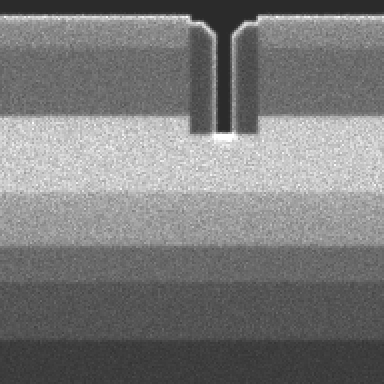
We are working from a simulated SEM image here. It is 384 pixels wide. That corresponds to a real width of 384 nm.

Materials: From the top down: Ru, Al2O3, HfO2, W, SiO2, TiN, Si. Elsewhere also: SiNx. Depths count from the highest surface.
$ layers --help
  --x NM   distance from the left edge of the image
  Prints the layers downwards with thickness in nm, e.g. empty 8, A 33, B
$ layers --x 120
Ru 32, Al2O3 68, HfO2 76, W 54, SiO2 36, TiN 58, Si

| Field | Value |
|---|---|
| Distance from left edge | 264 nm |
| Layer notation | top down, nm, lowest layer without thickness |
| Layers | Ru 32, Al2O3 68, HfO2 76, W 54, SiO2 36, TiN 58, Si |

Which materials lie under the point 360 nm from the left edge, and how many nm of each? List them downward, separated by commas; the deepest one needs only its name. Ru 32, Al2O3 68, HfO2 76, W 54, SiO2 36, TiN 58, Si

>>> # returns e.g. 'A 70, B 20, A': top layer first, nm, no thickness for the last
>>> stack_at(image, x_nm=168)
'Ru 32, Al2O3 68, HfO2 76, W 54, SiO2 36, TiN 58, Si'